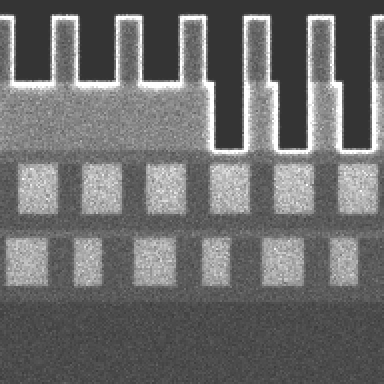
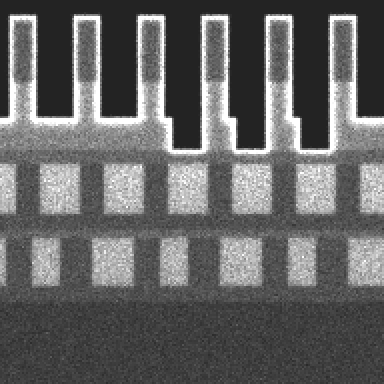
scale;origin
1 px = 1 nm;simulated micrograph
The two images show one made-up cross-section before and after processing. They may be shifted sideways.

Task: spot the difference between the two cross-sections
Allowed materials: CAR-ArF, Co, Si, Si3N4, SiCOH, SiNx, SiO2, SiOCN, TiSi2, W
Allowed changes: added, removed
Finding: removed SiO2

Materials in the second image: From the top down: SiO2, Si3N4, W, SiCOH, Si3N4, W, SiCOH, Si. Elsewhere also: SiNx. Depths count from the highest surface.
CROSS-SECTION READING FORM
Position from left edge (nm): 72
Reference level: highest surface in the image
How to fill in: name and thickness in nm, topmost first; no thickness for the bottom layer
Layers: empty 102, SiO2 32, Si3N4 14, W 50, SiCOH 16, Si3N4 8, SiCOH 64, Si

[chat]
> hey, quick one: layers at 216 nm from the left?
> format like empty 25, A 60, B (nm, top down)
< SiNx 66, SiO2 68, Si3N4 14, SiCOH 66, Si3N4 8, SiCOH 64, Si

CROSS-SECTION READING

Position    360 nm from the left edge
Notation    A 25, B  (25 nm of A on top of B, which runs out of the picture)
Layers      empty 102, SiO2 32, Si3N4 14, W 50, SiCOH 16, Si3N4 8, W 48, SiCOH 16, Si